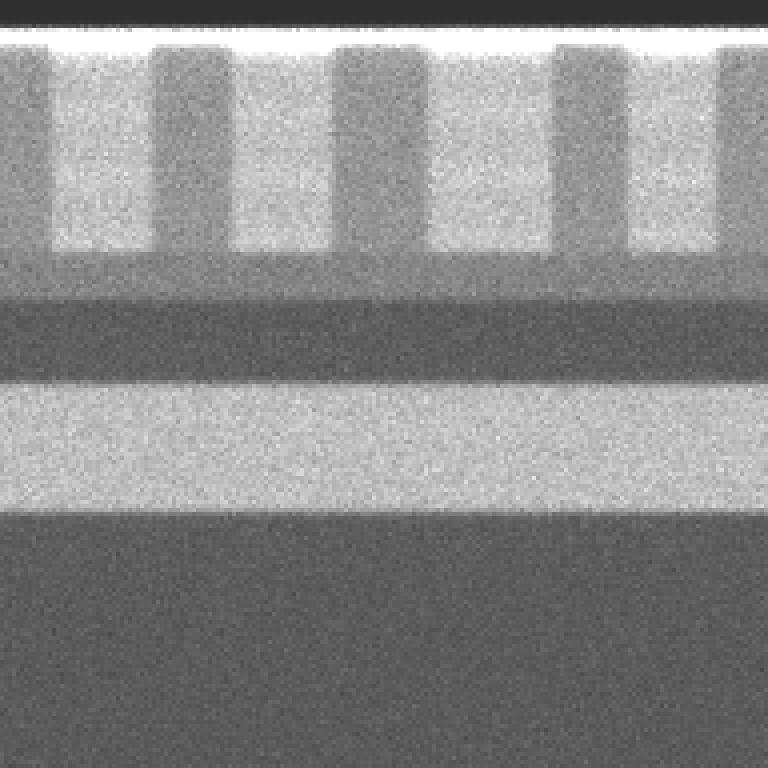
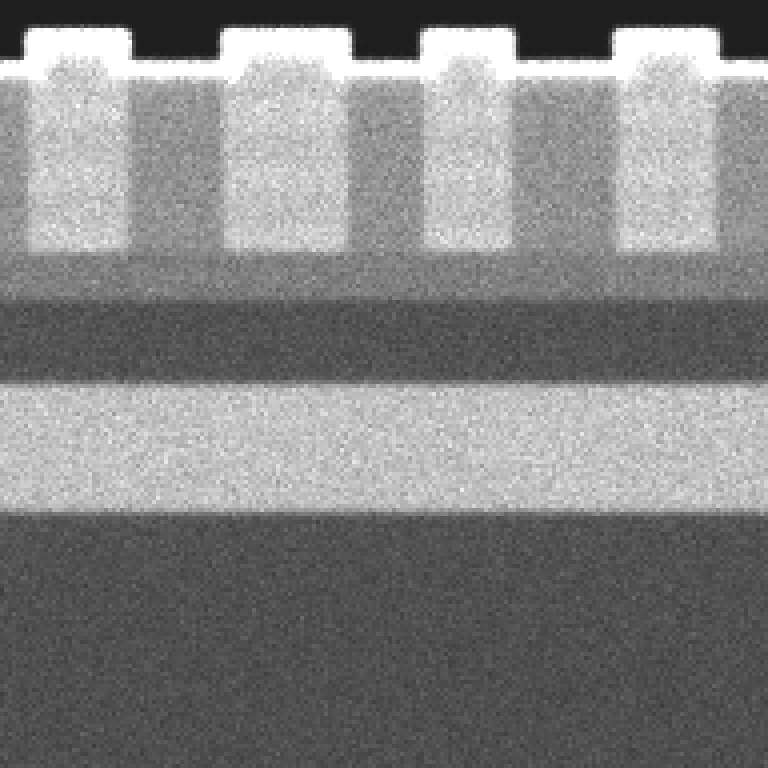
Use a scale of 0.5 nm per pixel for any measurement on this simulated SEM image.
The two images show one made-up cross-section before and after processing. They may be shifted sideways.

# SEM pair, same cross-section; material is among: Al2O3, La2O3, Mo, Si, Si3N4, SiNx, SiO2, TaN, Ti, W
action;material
removed;Si3N4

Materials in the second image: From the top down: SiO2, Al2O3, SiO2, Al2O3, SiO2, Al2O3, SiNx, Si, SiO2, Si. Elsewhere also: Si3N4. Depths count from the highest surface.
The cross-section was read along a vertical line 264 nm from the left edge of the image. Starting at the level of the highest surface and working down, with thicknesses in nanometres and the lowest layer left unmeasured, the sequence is empty 16, Si3N4 94, SiNx 24, Si 42, SiO2 64, Si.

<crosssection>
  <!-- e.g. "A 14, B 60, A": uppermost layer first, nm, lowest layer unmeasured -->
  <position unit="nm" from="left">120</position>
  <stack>SiO2 34, Al2O3 12, SiO2 20, Al2O3 12, SiO2 20, Al2O3 12, SiNx 24, Si 42, SiO2 64, Si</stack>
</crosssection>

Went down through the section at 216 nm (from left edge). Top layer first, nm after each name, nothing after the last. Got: SiO2 34, Al2O3 12, SiO2 20, Al2O3 12, SiO2 20, Al2O3 12, SiNx 24, Si 42, SiO2 64, Si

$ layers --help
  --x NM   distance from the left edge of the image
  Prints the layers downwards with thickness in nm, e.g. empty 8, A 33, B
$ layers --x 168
SiO2 34, Al2O3 12, SiO2 20, Al2O3 12, SiO2 20, Al2O3 12, SiNx 24, Si 42, SiO2 64, Si